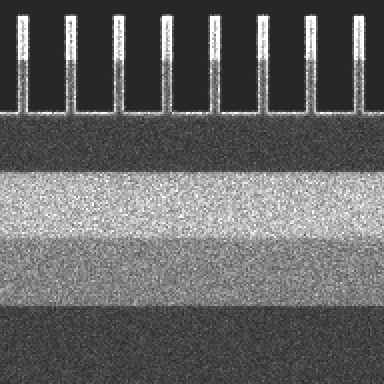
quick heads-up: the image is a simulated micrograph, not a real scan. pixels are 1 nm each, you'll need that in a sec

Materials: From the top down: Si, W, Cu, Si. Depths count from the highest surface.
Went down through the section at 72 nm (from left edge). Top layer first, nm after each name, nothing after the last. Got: Si 156, W 66, Cu 68, Si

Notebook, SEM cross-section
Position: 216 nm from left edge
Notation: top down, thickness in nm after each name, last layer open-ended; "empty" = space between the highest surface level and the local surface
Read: Si 156, W 66, Cu 68, Si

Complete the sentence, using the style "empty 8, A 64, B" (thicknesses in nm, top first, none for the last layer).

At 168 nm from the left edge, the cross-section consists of Si 156, W 66, Cu 68, Si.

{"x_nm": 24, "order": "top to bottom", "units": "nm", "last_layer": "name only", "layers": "Si 156, W 66, Cu 68, Si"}